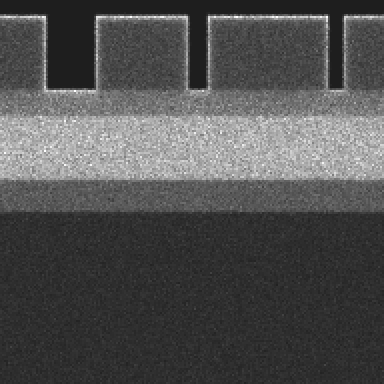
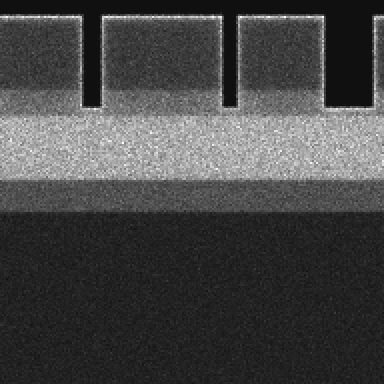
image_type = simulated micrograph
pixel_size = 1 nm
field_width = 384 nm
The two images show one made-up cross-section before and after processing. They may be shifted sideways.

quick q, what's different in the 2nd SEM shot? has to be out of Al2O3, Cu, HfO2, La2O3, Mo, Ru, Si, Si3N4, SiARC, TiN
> Ru removed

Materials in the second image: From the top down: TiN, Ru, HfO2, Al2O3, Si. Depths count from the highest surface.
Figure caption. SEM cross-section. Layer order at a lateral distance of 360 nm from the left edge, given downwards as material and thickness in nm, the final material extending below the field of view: empty 92, Ru 8, HfO2 64, Al2O3 32, Si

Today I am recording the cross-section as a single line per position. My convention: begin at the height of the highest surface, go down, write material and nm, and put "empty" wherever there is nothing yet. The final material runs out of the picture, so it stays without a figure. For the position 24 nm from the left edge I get TiN 74, Ru 26, HfO2 64, Al2O3 32, Si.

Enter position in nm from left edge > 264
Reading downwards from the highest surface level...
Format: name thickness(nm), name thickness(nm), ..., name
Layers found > TiN 74, Ru 26, HfO2 64, Al2O3 32, Si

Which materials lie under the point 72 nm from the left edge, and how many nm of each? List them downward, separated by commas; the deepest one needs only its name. TiN 74, Ru 26, HfO2 64, Al2O3 32, Si